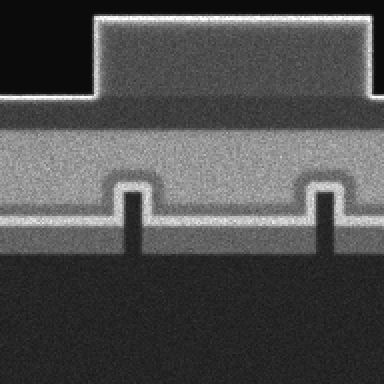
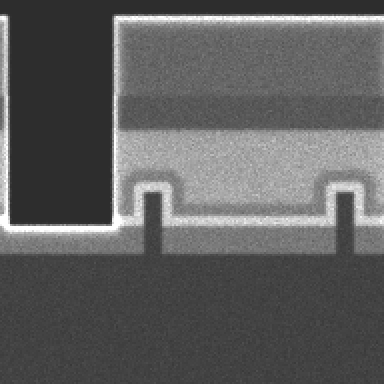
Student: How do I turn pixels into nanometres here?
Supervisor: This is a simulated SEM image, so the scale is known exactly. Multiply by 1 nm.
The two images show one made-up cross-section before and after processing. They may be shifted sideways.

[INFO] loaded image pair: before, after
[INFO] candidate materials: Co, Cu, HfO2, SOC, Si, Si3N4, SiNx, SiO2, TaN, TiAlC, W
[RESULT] removed Co and HfO2 and SiNx and W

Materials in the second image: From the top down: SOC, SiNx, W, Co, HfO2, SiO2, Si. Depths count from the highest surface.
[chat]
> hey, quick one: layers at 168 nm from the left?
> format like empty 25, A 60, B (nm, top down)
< SOC 80, SiNx 34, W 40, Co 14, HfO2 42, SiO2 28, Si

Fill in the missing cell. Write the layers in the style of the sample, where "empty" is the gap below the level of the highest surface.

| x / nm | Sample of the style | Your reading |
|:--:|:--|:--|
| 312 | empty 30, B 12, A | SOC 80, SiNx 34, W 74, Co 12, HfO2 10, SiO2 28, Si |